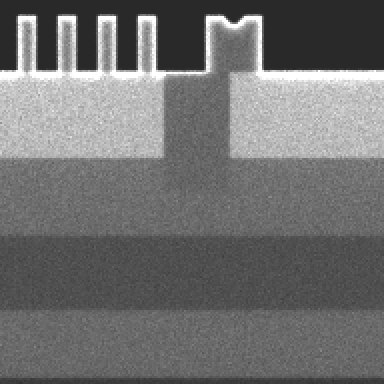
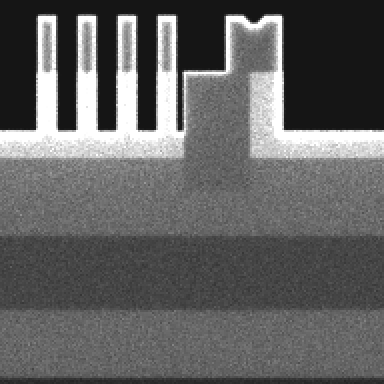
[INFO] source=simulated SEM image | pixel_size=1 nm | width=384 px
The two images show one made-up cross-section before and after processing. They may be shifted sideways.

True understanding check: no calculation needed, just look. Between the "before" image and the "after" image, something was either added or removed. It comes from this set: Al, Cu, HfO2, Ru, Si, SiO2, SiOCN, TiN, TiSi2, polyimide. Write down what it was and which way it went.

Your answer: HfO2 (removed)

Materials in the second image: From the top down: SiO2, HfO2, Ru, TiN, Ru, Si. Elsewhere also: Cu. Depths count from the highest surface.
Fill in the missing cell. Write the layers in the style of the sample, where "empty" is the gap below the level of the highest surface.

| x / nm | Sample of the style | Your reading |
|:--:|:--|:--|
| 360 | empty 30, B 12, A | empty 116, HfO2 26, Ru 78, TiN 74, Ru 68, Si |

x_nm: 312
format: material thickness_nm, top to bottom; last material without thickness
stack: empty 116, HfO2 26, Ru 78, TiN 74, Ru 68, Si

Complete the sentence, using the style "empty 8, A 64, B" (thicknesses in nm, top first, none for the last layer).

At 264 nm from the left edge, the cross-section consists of SiO2 56, HfO2 86, Ru 78, TiN 74, Ru 68, Si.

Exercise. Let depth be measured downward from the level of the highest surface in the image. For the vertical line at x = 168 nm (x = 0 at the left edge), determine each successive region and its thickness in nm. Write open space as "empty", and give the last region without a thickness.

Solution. SiO2 56, HfO2 86, Ru 78, TiN 74, Ru 68, Si